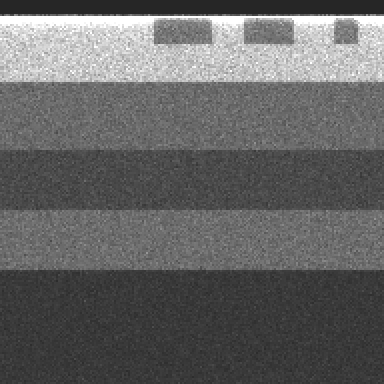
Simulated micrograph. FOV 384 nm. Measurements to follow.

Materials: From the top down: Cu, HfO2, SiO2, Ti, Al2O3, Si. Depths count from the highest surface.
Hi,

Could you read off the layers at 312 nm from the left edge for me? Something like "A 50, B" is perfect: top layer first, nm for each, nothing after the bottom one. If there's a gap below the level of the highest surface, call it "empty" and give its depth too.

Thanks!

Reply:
HfO2 66, SiO2 68, Ti 60, Al2O3 60, Si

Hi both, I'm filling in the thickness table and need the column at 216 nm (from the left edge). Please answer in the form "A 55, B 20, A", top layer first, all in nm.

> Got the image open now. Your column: HfO2 66, SiO2 68, Ti 60, Al2O3 60, Si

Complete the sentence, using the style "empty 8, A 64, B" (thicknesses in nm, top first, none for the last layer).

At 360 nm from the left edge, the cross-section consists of HfO2 66, SiO2 68, Ti 60, Al2O3 60, Si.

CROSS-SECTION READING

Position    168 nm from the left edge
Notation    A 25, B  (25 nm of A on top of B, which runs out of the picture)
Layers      Cu 28, HfO2 38, SiO2 68, Ti 60, Al2O3 60, Si